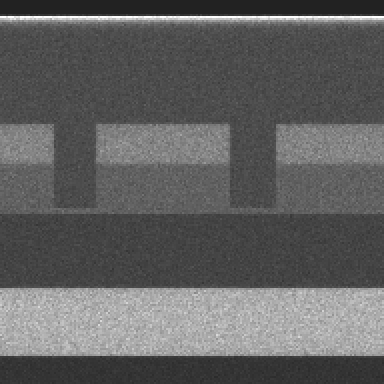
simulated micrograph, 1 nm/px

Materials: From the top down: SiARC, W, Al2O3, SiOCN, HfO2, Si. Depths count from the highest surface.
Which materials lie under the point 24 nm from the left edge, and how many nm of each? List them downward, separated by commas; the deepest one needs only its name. SiARC 108, W 40, Al2O3 50, SiOCN 74, HfO2 68, Si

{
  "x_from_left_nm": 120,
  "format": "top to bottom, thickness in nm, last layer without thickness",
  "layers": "SiARC 108, W 40, Al2O3 50, SiOCN 74, HfO2 68, Si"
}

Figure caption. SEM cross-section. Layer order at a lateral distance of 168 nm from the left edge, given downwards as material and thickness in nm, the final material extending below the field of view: SiARC 108, W 40, Al2O3 50, SiOCN 74, HfO2 68, Si